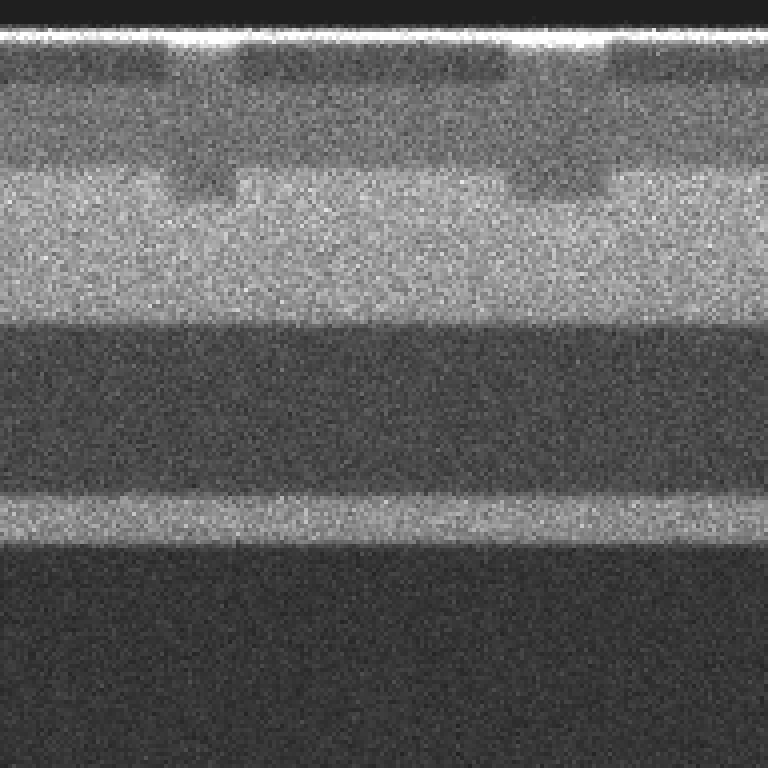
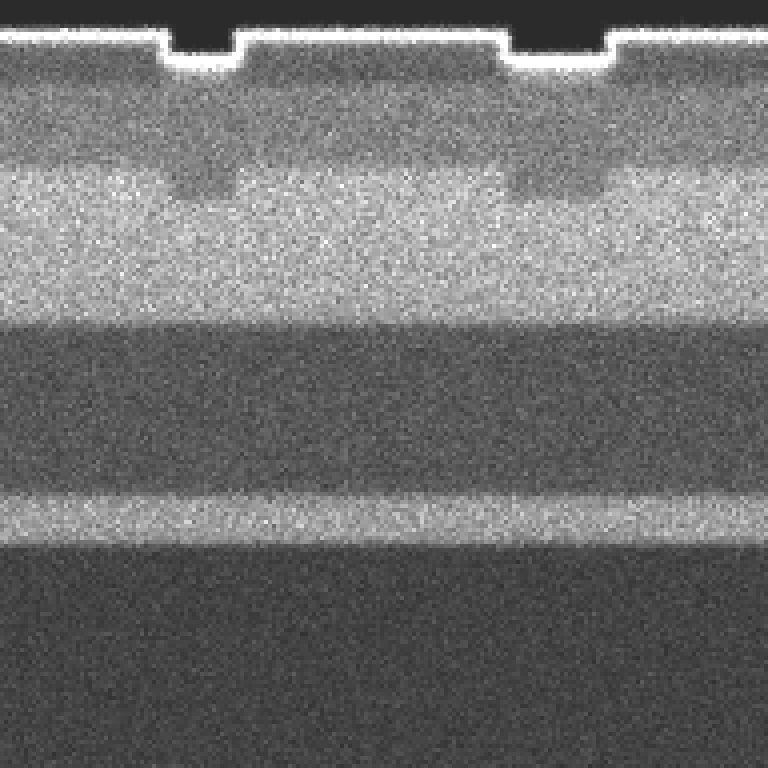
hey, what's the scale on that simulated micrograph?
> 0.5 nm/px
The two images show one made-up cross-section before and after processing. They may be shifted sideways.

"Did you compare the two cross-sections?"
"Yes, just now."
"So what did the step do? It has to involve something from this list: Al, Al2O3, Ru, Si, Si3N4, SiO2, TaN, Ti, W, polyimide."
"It removed SiO2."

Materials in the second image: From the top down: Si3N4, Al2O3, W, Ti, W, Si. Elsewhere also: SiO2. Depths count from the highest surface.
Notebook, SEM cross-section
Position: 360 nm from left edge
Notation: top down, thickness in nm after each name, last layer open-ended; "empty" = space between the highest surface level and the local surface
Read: Si3N4 26, Al2O3 42, W 78, Ti 86, W 24, Si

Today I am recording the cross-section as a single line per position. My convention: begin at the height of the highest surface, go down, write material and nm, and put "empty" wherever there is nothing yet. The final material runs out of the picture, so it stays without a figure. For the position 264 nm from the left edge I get empty 12, SiO2 72, W 62, Ti 86, W 24, Si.